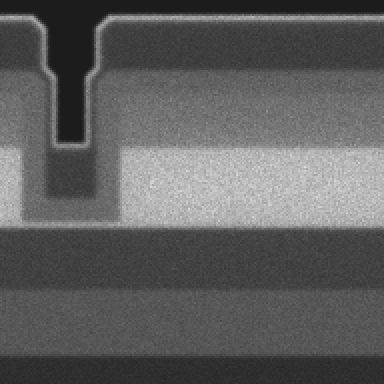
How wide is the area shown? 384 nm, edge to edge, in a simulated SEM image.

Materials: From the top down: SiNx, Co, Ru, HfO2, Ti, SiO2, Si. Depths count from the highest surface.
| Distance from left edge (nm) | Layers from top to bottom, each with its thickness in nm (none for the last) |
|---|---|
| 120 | SiNx 54, Co 24, Ru 54, HfO2 80, Ti 62, SiO2 66, Si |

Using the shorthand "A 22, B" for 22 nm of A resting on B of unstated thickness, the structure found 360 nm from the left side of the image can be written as SiNx 54, Co 24, Ru 54, HfO2 80, Ti 62, SiO2 66, Si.